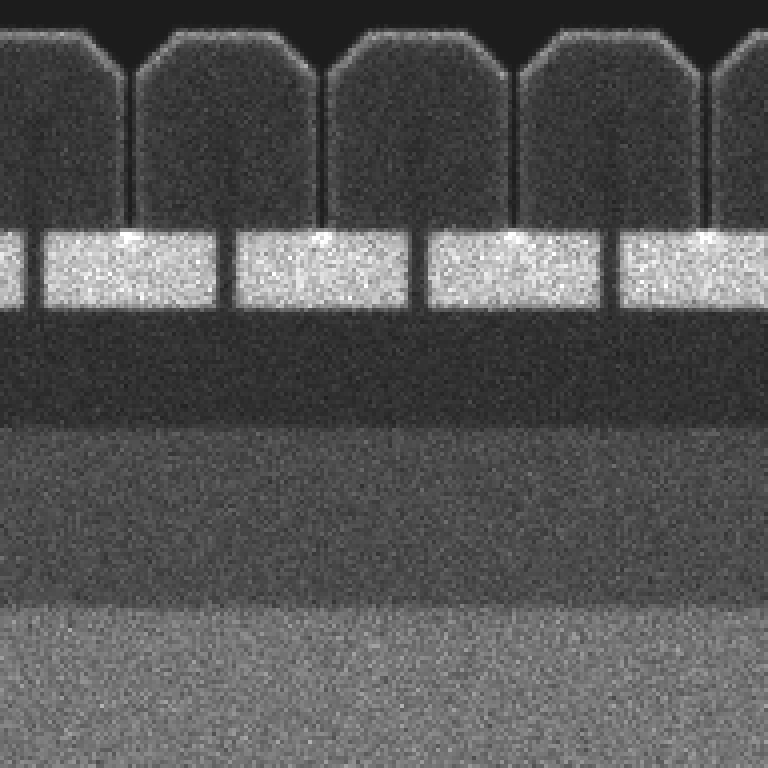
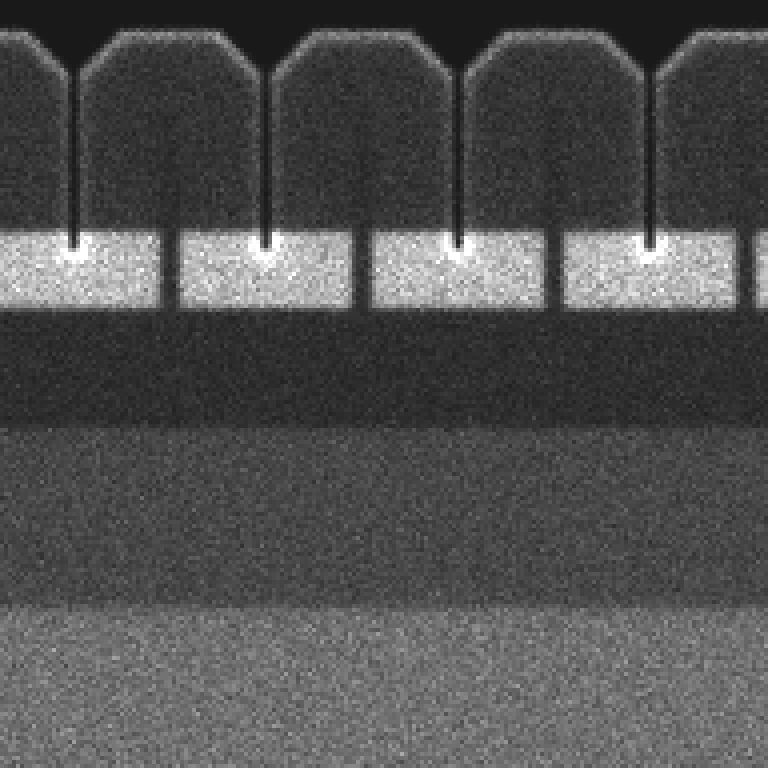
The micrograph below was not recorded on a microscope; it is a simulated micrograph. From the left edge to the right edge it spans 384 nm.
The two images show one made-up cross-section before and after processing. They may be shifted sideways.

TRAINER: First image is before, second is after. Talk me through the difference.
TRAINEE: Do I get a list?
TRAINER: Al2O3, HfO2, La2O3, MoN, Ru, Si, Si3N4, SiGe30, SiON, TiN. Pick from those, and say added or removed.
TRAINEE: removed: HfO2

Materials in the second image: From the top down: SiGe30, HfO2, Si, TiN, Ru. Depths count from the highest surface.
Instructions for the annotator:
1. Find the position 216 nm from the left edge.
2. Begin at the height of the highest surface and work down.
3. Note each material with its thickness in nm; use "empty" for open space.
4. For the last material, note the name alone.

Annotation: empty 12, SiGe30 88, HfO2 38, Si 60, TiN 90, Ru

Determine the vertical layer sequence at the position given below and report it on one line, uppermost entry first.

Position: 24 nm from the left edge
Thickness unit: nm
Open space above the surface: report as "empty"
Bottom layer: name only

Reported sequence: empty 12, SiGe30 88, HfO2 38, Si 60, TiN 90, Ru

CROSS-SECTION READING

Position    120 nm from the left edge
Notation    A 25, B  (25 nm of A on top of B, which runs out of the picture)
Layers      empty 12, SiGe30 88, HfO2 38, Si 60, TiN 90, Ru